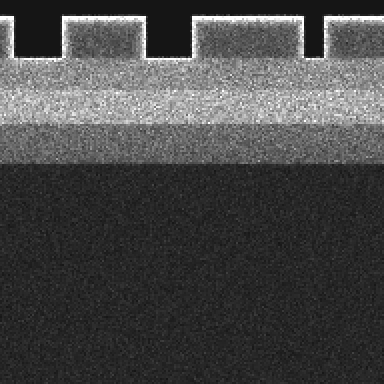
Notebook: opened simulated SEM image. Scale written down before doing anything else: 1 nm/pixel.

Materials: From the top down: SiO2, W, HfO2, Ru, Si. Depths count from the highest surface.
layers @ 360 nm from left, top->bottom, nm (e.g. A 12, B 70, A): SiO2 42, W 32, HfO2 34, Ru 40, Si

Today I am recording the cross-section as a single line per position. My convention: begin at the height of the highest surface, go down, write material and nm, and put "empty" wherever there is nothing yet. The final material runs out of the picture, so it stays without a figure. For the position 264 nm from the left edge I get SiO2 42, W 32, HfO2 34, Ru 40, Si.